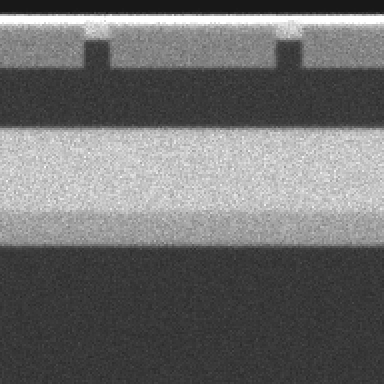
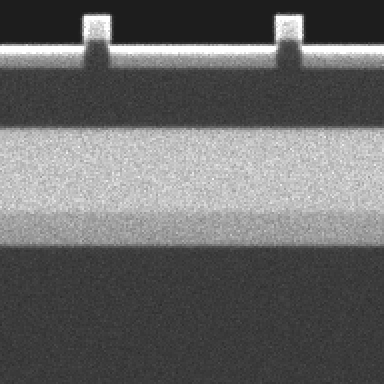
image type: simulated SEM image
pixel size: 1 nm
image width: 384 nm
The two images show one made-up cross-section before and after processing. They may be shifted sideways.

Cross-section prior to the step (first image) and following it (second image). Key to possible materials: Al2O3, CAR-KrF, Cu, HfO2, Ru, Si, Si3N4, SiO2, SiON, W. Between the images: SiO2 was removed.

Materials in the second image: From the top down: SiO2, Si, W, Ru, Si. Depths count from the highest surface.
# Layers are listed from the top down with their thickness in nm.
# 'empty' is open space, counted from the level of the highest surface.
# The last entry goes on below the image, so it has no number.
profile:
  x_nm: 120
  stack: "empty 30, SiO2 22, Si 60, W 84, Ru 34, Si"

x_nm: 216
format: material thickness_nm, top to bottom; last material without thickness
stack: empty 30, SiO2 22, Si 60, W 84, Ru 34, Si